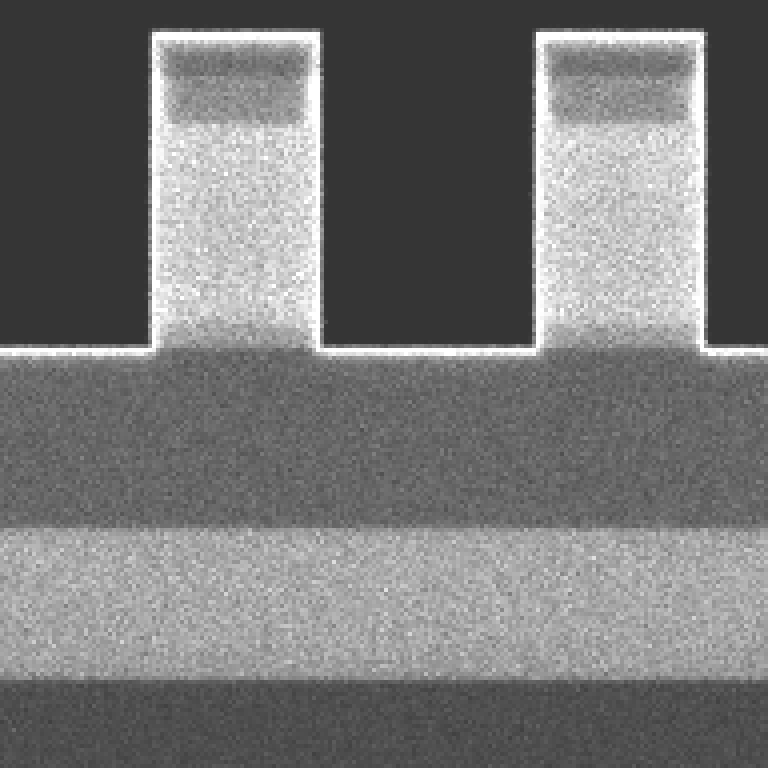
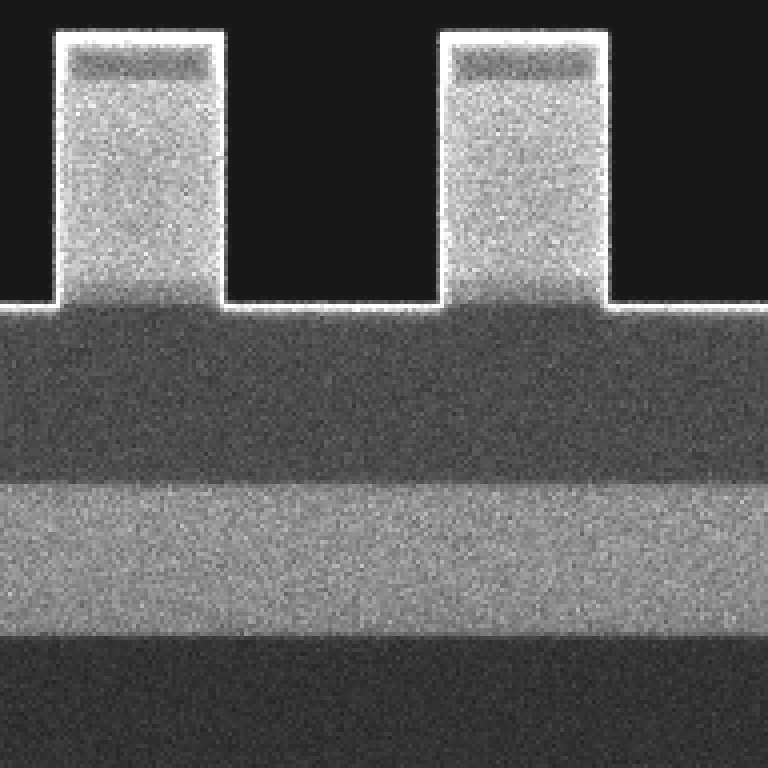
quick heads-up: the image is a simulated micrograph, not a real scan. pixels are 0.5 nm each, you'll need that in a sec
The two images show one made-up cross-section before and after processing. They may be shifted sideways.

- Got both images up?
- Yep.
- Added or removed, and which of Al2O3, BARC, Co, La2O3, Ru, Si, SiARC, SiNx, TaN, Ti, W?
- removed, SiARC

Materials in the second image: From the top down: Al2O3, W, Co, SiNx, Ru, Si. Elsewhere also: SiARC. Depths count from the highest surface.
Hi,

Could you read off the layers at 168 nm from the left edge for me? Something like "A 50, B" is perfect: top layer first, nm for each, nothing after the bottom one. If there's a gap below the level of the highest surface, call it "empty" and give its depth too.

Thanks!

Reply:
empty 136, SiNx 90, Ru 76, Si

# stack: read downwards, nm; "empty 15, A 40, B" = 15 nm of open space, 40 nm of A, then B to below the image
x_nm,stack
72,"Al2O3 24, W 100, Co 12, SiNx 90, Ru 76, Si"